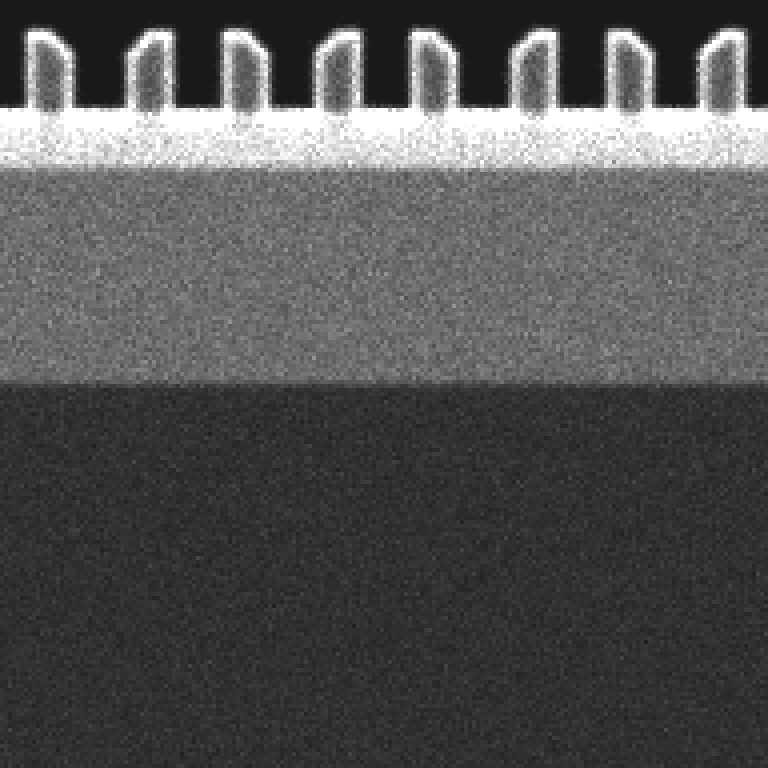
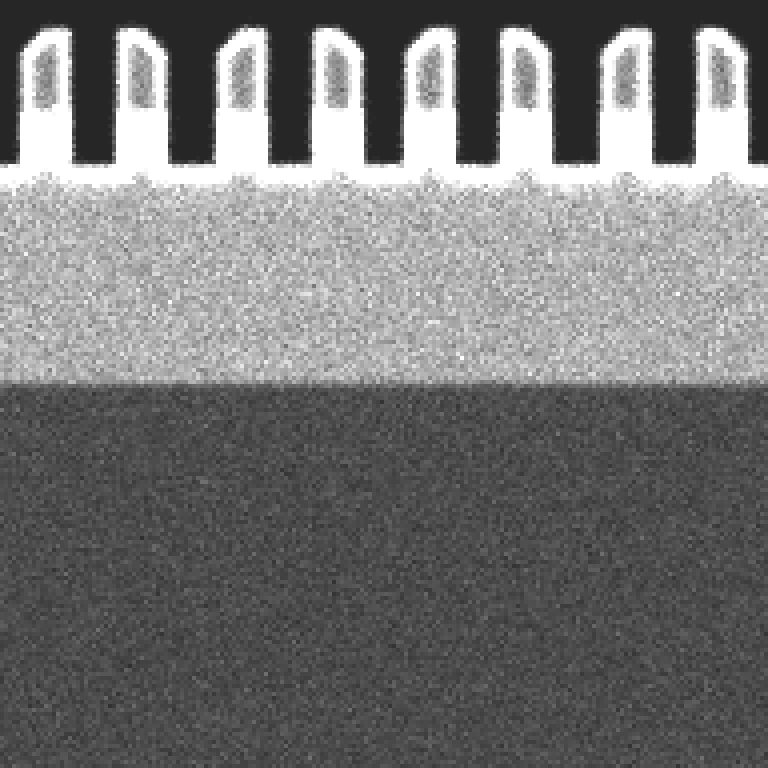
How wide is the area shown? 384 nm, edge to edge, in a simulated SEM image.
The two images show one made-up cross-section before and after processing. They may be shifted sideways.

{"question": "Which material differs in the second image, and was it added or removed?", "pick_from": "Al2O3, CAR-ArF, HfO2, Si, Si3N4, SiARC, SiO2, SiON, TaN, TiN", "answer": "HfO2, removed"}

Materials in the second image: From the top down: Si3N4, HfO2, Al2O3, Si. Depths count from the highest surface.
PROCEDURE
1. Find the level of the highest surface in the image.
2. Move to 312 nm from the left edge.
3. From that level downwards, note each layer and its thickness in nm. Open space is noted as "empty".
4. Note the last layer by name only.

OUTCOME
Si3N4 40, HfO2 28, Al2O3 108, Si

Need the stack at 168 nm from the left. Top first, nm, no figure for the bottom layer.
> Si3N4 40, HfO2 28, Al2O3 108, Si